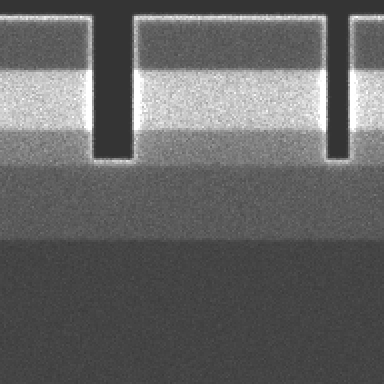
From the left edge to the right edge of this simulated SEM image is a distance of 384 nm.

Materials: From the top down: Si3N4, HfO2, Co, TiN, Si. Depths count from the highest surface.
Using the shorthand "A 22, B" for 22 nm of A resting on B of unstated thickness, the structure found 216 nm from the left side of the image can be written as Si3N4 54, HfO2 60, Co 36, TiN 74, Si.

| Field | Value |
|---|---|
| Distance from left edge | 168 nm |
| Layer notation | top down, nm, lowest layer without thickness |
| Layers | Si3N4 54, HfO2 60, Co 36, TiN 74, Si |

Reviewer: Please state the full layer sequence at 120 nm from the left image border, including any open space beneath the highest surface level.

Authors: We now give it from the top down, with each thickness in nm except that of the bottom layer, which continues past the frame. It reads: empty 144, Co 6, TiN 74, Si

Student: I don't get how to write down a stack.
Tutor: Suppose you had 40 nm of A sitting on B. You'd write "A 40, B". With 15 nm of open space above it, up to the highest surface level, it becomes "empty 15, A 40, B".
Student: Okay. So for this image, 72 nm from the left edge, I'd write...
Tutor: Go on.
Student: Si3N4 54, HfO2 60, Co 36, TiN 74, Si